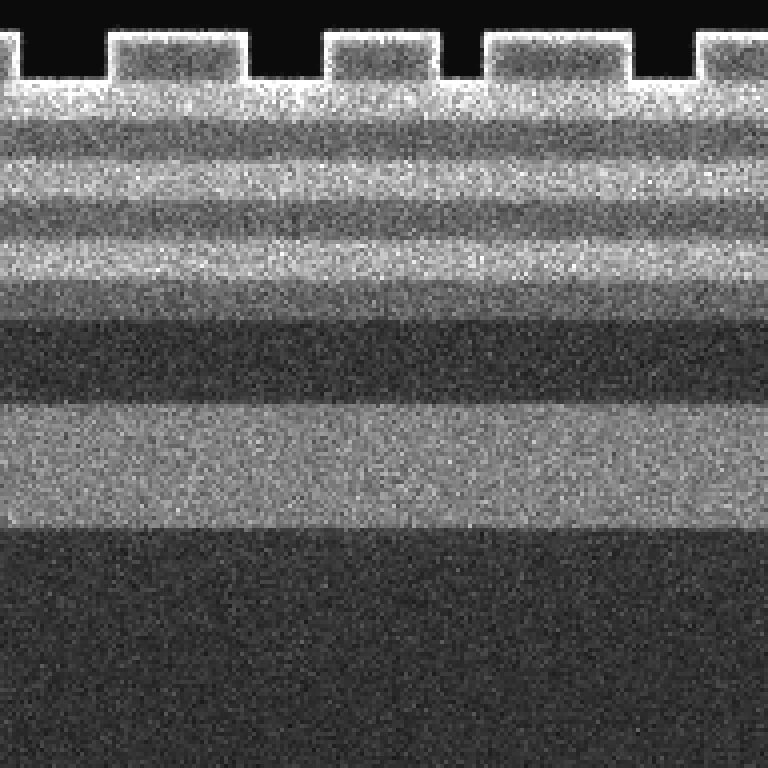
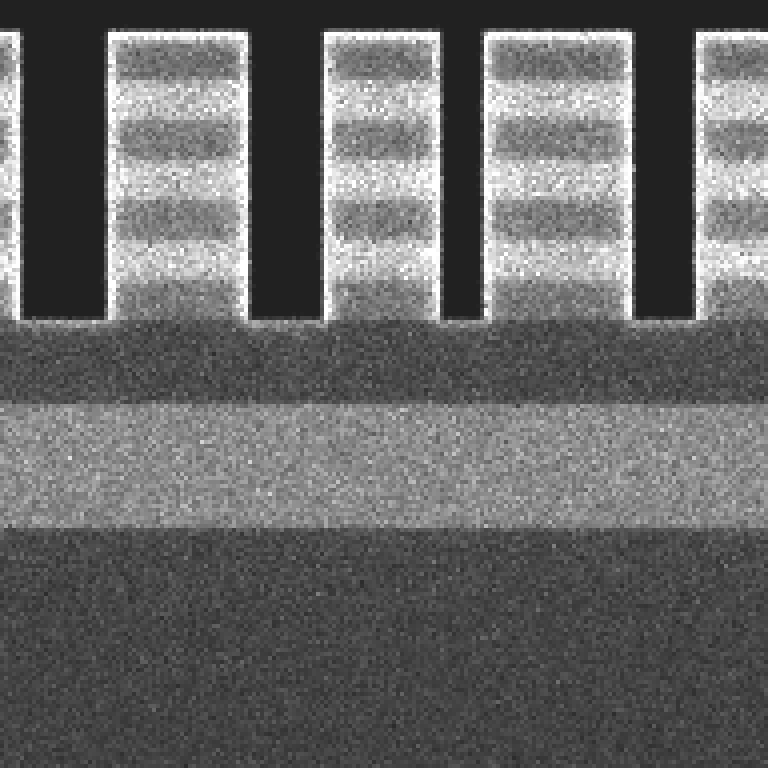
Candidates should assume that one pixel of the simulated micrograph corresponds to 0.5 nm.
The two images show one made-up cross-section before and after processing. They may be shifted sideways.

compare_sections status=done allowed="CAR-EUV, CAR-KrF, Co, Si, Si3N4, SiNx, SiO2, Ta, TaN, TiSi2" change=removed material="Co and Si3N4"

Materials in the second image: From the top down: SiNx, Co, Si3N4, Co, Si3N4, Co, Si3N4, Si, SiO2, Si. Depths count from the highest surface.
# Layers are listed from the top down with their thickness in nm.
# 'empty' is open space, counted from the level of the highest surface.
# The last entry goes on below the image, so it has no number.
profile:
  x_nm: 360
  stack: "SiNx 24, Co 20, Si3N4 20, Co 20, Si3N4 20, Co 20, Si3N4 20, Si 42, SiO2 62, Si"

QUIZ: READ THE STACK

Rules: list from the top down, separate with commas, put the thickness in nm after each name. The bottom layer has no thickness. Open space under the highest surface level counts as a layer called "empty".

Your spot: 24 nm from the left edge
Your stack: empty 144, Si 42, SiO2 62, Si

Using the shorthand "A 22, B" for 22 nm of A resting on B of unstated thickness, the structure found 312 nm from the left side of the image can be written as SiNx 24, Co 20, Si3N4 20, Co 20, Si3N4 20, Co 20, Si3N4 20, Si 42, SiO2 62, Si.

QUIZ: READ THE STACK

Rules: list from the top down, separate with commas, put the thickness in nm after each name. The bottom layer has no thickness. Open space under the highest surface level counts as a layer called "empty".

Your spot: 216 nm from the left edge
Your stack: SiNx 24, Co 20, Si3N4 20, Co 20, Si3N4 20, Co 20, Si3N4 20, Si 42, SiO2 62, Si